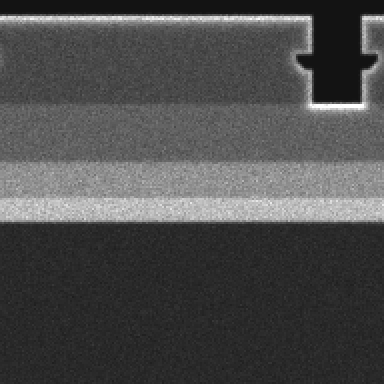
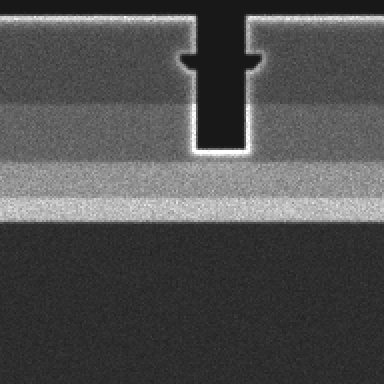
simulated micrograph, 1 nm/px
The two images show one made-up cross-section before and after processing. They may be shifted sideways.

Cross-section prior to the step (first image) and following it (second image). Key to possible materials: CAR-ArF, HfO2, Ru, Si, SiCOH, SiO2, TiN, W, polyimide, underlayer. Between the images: SiO2 was removed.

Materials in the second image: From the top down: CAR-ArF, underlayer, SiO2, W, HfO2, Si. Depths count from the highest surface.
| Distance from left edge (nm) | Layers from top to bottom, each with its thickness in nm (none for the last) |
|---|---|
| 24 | CAR-ArF 38, underlayer 50, SiO2 58, W 36, HfO2 24, Si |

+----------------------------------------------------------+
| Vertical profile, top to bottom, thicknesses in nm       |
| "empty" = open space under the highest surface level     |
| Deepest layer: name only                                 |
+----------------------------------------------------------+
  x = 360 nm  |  CAR-ArF 38, underlayer 50, SiO2 58, W 36, HfO2 24, Si